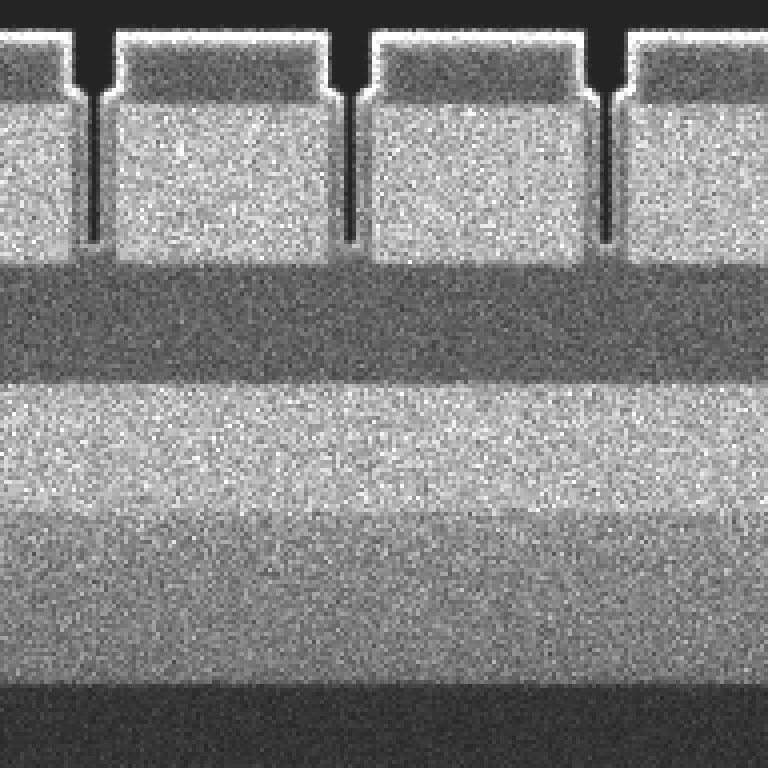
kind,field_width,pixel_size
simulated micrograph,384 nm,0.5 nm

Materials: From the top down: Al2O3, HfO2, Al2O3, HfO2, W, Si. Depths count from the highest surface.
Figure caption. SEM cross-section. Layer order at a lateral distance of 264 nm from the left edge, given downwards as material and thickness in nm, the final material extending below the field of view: Al2O3 36, HfO2 80, Al2O3 60, HfO2 64, W 86, Si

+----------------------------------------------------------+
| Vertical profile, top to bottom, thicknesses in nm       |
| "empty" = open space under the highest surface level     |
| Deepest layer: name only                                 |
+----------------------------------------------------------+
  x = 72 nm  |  Al2O3 36, HfO2 80, Al2O3 60, HfO2 64, W 86, Si